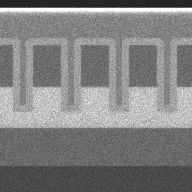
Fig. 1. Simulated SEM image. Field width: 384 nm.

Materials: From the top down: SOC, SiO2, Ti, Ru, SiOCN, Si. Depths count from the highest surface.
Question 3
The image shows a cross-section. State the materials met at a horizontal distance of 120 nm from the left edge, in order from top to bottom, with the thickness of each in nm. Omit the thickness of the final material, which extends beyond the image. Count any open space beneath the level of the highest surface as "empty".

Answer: SOC 60, SiO2 14, Ti 84, Ru 82, SiOCN 76, Si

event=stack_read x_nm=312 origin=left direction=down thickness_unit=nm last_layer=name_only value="SOC 60, SiO2 14, Ti 84, Ru 82, SiOCN 76, Si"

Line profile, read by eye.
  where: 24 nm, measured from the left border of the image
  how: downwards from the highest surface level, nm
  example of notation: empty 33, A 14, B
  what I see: SOC 60, SiO2 14, Ti 84, Ru 82, SiOCN 76, Si